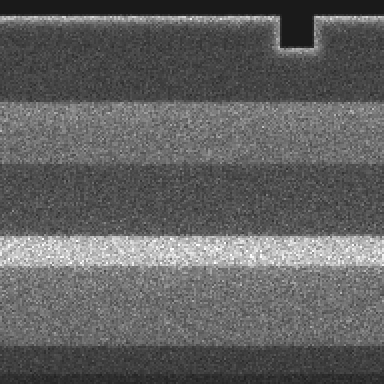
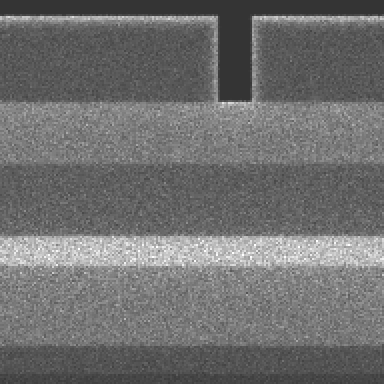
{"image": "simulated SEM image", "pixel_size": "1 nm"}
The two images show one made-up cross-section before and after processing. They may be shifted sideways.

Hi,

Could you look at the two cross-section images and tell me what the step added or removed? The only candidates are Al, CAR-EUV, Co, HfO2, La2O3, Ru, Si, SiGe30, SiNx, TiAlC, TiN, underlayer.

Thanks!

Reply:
removed underlayer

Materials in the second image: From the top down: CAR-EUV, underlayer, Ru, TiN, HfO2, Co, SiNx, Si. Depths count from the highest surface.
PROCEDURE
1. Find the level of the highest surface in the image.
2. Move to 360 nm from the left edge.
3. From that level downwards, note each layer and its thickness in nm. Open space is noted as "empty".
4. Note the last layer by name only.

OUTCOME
CAR-EUV 32, underlayer 54, Ru 62, TiN 72, HfO2 30, Co 80, SiNx 28, Si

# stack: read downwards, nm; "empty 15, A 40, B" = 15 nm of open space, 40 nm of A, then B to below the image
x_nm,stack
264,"CAR-EUV 32, underlayer 54, Ru 62, TiN 72, HfO2 30, Co 80, SiNx 28, Si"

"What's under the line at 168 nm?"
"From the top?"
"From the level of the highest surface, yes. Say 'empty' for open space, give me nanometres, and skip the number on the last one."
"CAR-EUV 32, underlayer 54, Ru 62, TiN 72, HfO2 30, Co 80, SiNx 28, Si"